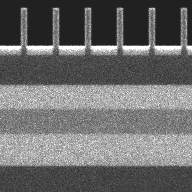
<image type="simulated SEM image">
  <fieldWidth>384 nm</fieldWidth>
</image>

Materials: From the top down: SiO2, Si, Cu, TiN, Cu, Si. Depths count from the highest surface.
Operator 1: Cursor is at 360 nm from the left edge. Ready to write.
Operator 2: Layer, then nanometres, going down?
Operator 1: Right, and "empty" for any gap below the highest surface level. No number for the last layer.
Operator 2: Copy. empty 76, SiO2 18, Si 60, Cu 48, TiN 50, Cu 64, Si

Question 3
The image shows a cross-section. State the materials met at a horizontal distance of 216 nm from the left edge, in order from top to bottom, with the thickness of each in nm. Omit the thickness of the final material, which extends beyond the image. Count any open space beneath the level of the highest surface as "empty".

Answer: empty 76, SiO2 18, Si 60, Cu 48, TiN 50, Cu 64, Si